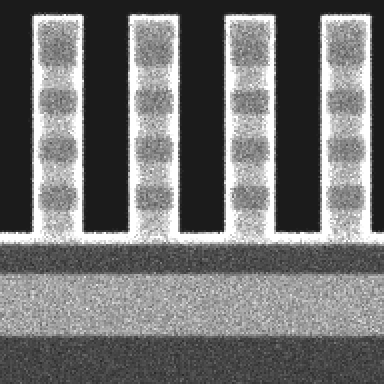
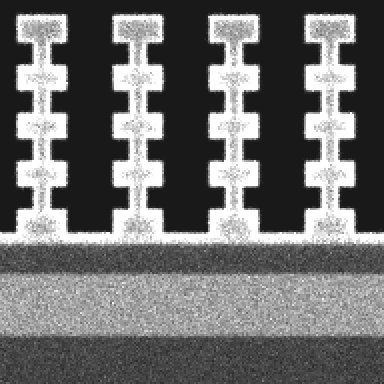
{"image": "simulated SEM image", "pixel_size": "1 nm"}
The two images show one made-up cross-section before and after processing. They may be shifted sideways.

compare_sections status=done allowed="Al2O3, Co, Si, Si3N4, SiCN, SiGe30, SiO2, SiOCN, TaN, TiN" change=removed material="Si3N4"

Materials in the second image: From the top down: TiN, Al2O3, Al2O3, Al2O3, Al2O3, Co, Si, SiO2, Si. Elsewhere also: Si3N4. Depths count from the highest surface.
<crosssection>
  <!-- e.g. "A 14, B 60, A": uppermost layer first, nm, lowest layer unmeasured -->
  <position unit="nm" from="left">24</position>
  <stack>TiN 26, empty 24, Al2O3 24, empty 24, Al2O3 24, empty 24, Al2O3 24, empty 24, Al2O3 24, Co 10, Si 30, SiO2 62, Si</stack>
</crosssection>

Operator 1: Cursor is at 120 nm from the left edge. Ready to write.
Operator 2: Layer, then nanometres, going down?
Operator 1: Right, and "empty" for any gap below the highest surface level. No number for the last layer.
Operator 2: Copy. TiN 26, empty 24, Al2O3 24, empty 24, Al2O3 24, empty 24, Al2O3 24, empty 24, Al2O3 24, Co 10, Si 30, SiO2 62, Si